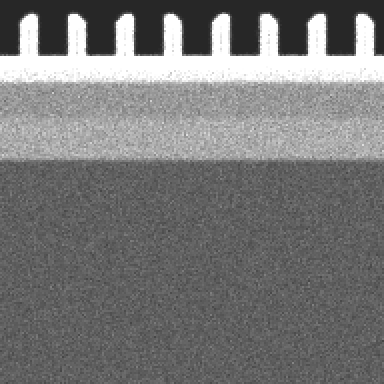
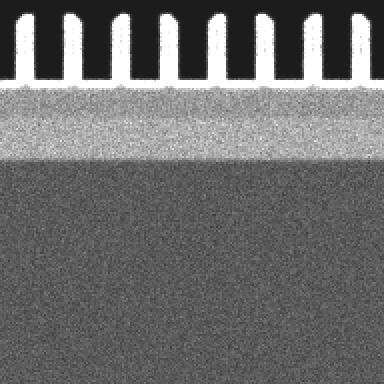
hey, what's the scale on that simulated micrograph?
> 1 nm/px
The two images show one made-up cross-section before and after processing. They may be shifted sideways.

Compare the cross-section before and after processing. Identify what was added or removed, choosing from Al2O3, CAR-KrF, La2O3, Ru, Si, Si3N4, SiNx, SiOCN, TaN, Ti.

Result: Al2O3 removed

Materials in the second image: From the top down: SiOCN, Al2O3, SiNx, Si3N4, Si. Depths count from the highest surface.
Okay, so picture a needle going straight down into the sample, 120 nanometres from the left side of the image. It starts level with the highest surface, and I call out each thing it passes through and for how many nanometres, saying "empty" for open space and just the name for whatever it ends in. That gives SiOCN 42, Al2O3 24, SiNx 36, Si3N4 42, Si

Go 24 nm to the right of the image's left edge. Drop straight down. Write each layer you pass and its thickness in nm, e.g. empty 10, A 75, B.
SiOCN 42, Al2O3 24, SiNx 36, Si3N4 42, Si